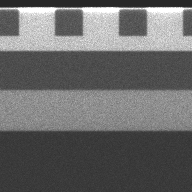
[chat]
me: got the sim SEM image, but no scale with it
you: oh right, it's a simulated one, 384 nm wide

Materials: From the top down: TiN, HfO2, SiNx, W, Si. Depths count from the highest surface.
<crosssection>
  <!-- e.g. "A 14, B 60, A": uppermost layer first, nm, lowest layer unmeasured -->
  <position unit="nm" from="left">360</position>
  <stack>HfO2 86, SiNx 78, W 82, Si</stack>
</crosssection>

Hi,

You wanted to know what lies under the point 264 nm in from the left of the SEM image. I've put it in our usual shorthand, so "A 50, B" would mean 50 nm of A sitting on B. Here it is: TiN 56, HfO2 30, SiNx 78, W 82, Si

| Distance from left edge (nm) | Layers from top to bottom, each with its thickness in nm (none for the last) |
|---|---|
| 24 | TiN 56, HfO2 30, SiNx 78, W 82, Si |